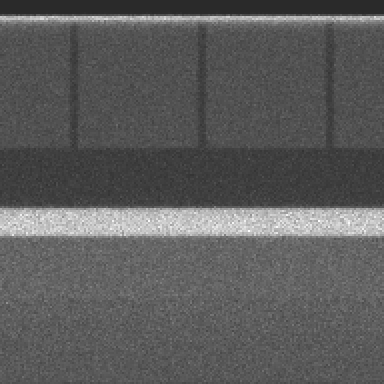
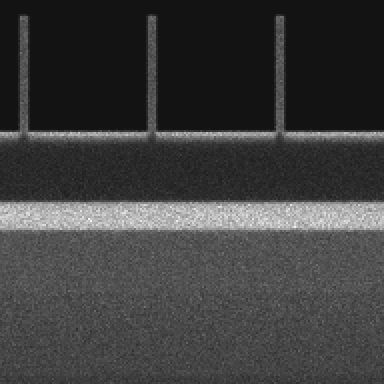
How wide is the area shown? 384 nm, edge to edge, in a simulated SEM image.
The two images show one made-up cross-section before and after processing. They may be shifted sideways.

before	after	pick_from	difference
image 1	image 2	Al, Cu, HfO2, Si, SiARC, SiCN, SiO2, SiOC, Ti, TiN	SiARC removed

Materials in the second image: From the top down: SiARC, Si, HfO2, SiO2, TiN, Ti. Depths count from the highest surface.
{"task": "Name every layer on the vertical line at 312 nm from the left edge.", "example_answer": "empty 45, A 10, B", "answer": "empty 116, SiARC 10, Si 60, HfO2 28, SiO2 62, TiN 84, Ti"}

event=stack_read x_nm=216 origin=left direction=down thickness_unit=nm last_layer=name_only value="empty 116, SiARC 10, Si 60, HfO2 28, SiO2 62, TiN 84, Ti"